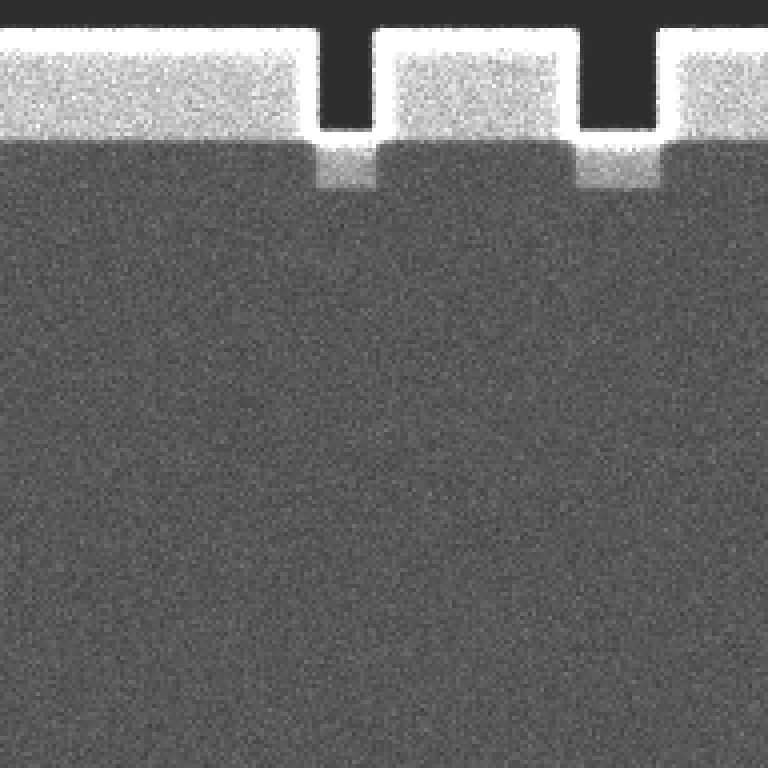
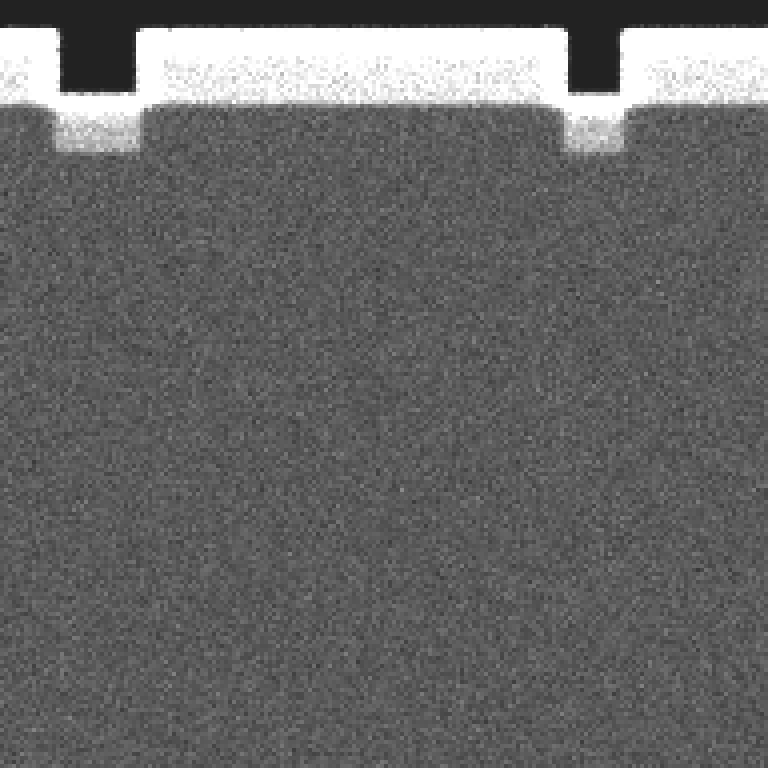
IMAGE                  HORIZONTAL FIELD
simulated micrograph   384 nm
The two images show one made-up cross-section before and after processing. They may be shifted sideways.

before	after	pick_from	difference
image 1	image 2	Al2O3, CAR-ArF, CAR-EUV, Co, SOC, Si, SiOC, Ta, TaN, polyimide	Al2O3 removed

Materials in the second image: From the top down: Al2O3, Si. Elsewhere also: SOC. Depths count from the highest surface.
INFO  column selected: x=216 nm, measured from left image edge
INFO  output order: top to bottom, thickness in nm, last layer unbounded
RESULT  Al2O3 36, Si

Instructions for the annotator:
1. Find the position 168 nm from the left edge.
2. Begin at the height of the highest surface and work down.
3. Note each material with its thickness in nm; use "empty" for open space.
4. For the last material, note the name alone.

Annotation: Al2O3 36, Si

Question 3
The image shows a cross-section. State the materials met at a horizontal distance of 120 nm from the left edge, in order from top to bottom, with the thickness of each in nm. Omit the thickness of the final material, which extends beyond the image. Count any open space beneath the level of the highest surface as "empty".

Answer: Al2O3 36, Si